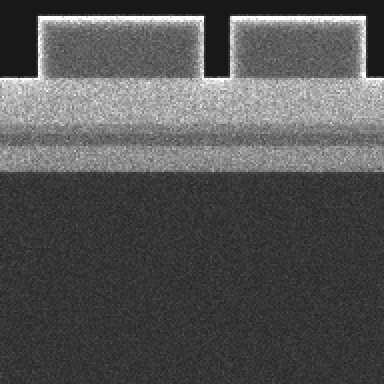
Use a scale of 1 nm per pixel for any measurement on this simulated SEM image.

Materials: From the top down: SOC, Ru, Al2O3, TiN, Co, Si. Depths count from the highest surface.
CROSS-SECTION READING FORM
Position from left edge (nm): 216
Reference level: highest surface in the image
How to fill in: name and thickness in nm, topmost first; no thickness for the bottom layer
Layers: empty 62, Ru 46, Al2O3 10, TiN 12, Co 26, Si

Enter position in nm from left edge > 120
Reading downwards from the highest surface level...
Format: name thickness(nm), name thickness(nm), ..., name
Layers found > SOC 62, Ru 46, Al2O3 10, TiN 12, Co 26, Si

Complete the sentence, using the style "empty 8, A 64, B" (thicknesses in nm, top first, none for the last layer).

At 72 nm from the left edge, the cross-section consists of SOC 62, Ru 46, Al2O3 10, TiN 12, Co 26, Si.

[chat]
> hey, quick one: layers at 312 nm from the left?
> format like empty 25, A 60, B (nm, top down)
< SOC 62, Ru 46, Al2O3 10, TiN 12, Co 26, Si